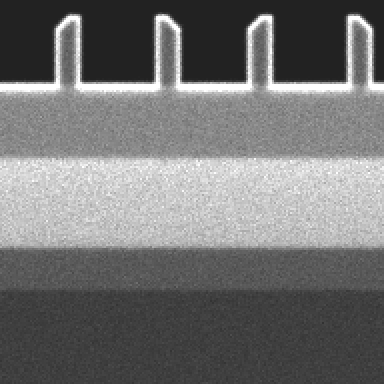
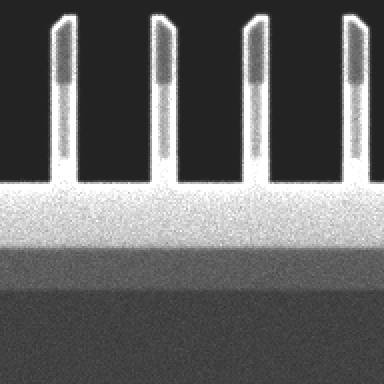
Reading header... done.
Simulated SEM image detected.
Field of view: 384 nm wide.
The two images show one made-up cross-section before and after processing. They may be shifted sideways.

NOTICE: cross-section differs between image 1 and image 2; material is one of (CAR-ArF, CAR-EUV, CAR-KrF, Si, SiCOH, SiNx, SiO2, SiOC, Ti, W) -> removed: SiO2 and W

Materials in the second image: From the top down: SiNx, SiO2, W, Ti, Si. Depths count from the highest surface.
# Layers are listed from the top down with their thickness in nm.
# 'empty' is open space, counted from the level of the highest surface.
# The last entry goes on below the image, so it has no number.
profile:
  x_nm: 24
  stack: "empty 168, W 64, Ti 42, Si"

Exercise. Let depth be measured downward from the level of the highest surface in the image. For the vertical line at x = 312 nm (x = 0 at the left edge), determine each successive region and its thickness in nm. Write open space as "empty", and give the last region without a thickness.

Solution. empty 168, W 64, Ti 42, Si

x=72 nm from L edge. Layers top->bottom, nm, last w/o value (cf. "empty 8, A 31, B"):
SiNx 68, SiO2 74, W 90, Ti 42, Si